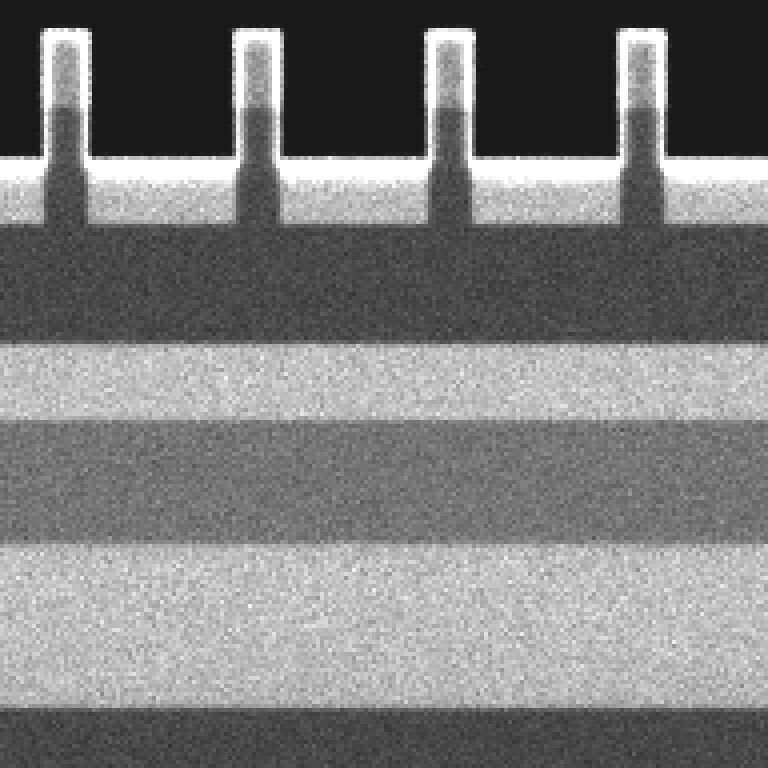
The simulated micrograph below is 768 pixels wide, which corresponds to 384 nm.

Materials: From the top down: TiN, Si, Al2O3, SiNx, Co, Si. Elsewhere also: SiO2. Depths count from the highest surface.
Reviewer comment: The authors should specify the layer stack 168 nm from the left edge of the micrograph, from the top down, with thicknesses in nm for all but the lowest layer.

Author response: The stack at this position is empty 64, SiO2 32, Si 60, Al2O3 38, SiNx 62, Co 82, Si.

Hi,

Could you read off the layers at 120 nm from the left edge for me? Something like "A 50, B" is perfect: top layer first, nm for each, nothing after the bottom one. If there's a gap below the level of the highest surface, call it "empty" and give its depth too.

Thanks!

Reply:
TiN 38, Si 118, Al2O3 38, SiNx 62, Co 82, Si